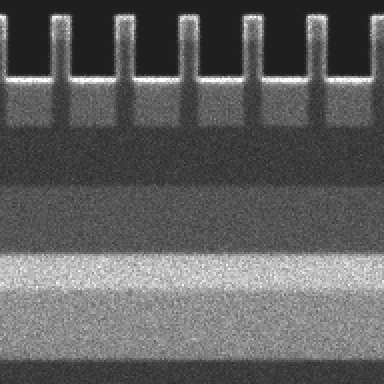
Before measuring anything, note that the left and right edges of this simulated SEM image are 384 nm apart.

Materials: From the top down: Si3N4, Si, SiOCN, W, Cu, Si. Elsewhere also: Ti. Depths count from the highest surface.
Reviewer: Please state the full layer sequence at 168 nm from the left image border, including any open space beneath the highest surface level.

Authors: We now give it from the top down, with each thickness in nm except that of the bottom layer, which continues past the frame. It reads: empty 62, Si3N4 48, Si 60, SiOCN 68, W 36, Cu 70, Si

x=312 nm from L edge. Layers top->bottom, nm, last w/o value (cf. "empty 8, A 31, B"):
Ti 24, Si 146, SiOCN 68, W 36, Cu 70, Si